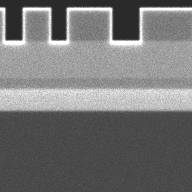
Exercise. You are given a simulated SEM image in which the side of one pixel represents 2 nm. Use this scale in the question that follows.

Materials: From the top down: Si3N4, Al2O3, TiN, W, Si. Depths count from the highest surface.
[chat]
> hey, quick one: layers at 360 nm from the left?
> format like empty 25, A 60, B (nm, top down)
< Si3N4 66, Al2O3 74, TiN 22, W 44, Si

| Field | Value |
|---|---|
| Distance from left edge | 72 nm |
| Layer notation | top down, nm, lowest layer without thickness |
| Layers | Si3N4 66, Al2O3 74, TiN 22, W 44, Si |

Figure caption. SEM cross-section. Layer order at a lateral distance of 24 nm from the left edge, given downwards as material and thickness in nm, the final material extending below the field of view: empty 66, Al2O3 74, TiN 22, W 44, Si